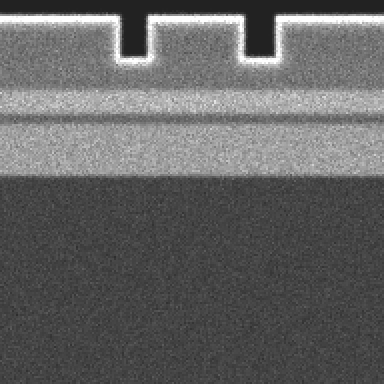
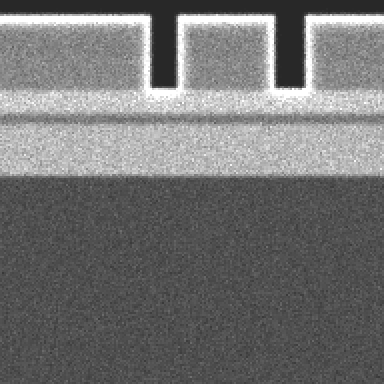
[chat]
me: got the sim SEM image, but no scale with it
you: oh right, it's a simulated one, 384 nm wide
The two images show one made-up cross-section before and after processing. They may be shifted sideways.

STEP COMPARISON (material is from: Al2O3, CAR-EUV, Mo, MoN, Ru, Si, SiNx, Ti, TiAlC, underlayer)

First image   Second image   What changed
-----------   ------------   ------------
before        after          underlayer, removed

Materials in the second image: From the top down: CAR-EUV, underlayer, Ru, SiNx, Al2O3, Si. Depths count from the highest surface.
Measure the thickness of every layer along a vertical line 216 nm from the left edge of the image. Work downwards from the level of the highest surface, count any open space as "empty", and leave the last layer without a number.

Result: CAR-EUV 42, underlayer 32, Ru 24, SiNx 10, Al2O3 52, Si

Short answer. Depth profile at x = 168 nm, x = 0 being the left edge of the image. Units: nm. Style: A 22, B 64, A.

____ empty 74, Ru 24, SiNx 10, Al2O3 52, Si